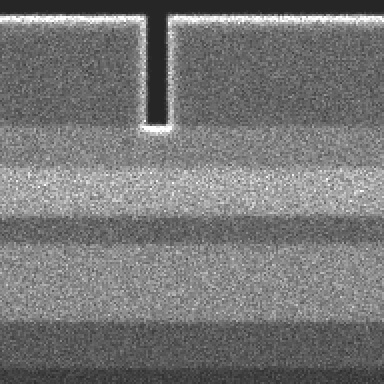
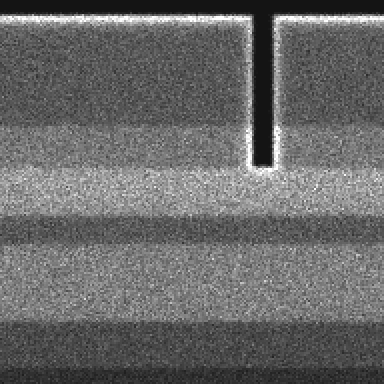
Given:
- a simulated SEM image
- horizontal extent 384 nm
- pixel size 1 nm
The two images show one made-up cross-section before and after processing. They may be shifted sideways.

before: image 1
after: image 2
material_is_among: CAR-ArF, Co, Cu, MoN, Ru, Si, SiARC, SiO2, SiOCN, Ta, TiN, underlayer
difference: SiO2, removed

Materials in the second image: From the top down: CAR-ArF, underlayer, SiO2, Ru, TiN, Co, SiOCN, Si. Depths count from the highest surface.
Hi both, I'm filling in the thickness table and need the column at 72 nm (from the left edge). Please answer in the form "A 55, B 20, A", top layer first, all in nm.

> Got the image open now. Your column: CAR-ArF 56, underlayer 54, SiO2 42, Ru 48, TiN 28, Co 78, SiOCN 46, Si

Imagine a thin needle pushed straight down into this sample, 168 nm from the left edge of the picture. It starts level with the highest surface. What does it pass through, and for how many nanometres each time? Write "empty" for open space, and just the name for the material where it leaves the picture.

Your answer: CAR-ArF 56, underlayer 54, SiO2 42, Ru 48, TiN 28, Co 78, SiOCN 46, Si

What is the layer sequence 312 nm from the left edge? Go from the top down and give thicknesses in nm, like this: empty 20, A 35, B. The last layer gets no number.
CAR-ArF 56, underlayer 54, SiO2 42, Ru 48, TiN 28, Co 78, SiOCN 46, Si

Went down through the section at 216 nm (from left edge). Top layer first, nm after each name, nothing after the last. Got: CAR-ArF 56, underlayer 54, SiO2 42, Ru 48, TiN 28, Co 78, SiOCN 46, Si